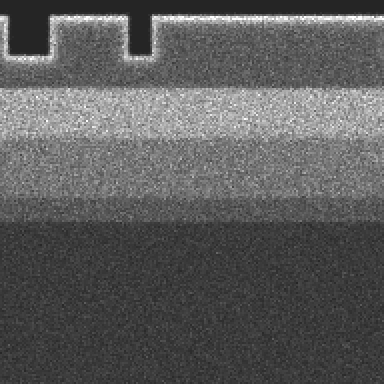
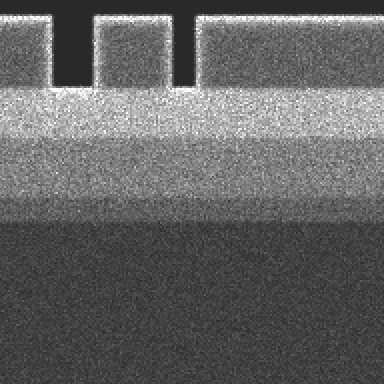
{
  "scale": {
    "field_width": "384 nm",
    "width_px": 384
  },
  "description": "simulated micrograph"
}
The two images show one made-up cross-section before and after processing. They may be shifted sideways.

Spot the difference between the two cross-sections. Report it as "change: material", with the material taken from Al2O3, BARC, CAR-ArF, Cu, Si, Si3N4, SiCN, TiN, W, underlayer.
removed: underlayer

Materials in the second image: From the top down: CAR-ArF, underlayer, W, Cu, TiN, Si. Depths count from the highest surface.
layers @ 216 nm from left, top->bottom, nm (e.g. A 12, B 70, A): CAR-ArF 40, underlayer 32, W 50, Cu 60, TiN 24, Si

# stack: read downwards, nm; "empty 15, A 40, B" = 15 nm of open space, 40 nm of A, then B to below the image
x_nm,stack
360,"CAR-ArF 40, underlayer 32, W 50, Cu 60, TiN 24, Si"